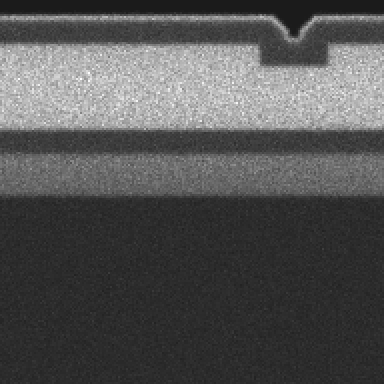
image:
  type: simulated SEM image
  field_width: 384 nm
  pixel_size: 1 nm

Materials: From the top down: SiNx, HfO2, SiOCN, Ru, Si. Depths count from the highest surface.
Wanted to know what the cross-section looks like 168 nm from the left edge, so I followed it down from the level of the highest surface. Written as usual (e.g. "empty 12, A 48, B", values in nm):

SiNx 28, HfO2 86, SiOCN 24, Ru 42, Si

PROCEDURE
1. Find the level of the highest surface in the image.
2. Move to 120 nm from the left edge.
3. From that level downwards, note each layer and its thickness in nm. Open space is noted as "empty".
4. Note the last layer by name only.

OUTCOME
SiNx 28, HfO2 86, SiOCN 24, Ru 42, Si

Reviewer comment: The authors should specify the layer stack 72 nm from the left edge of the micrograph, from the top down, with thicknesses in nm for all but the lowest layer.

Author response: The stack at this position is SiNx 28, HfO2 86, SiOCN 24, Ru 42, Si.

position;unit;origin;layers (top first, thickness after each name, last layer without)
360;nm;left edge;SiNx 28, HfO2 86, SiOCN 24, Ru 42, Si